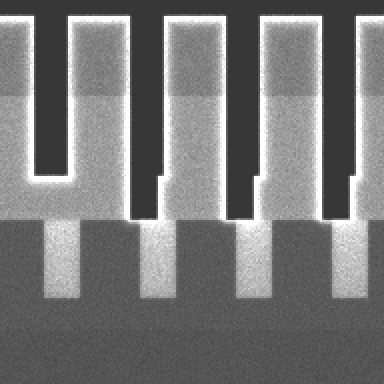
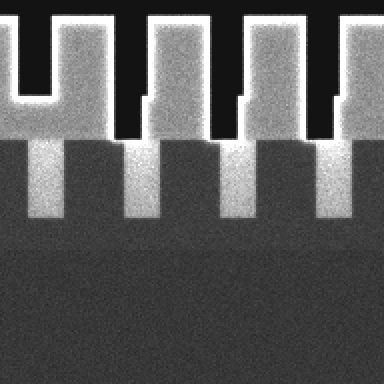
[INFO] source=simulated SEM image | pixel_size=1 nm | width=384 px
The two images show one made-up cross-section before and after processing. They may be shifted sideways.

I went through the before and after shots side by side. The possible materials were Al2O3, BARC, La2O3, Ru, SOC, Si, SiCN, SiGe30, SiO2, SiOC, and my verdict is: removed, SOC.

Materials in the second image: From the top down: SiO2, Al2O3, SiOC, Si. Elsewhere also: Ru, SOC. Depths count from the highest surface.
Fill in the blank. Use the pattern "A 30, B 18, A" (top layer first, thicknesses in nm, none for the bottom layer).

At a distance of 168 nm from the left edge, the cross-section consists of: SiO2 116, Al2O3 8, SiOC 110, Si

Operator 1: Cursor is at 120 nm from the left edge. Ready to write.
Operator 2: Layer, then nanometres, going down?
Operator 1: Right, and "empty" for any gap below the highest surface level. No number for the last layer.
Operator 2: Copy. empty 124, SiOC 110, Si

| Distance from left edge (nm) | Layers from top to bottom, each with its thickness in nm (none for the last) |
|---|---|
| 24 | empty 80, SiO2 36, Al2O3 8, SiOC 110, Si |